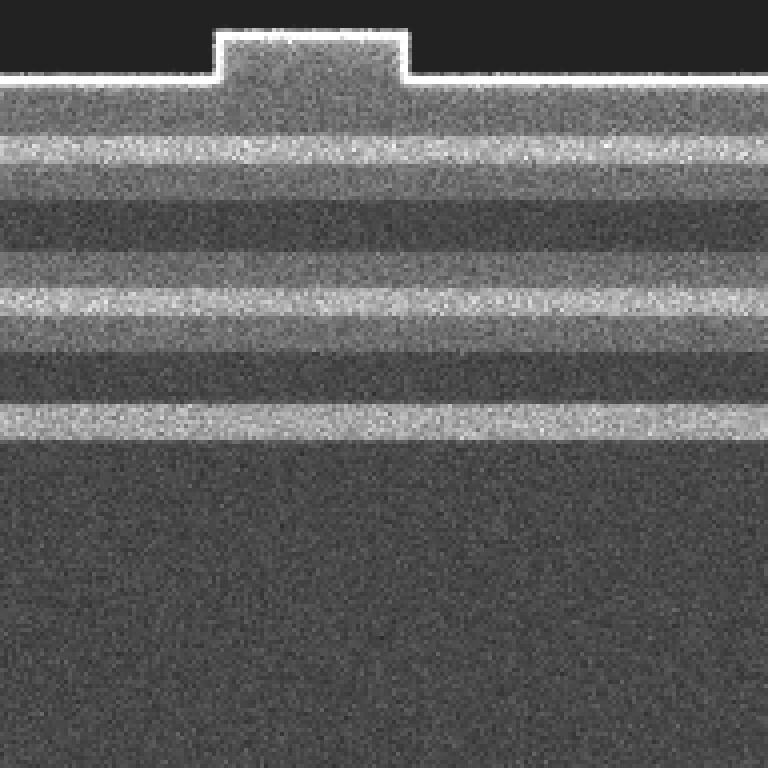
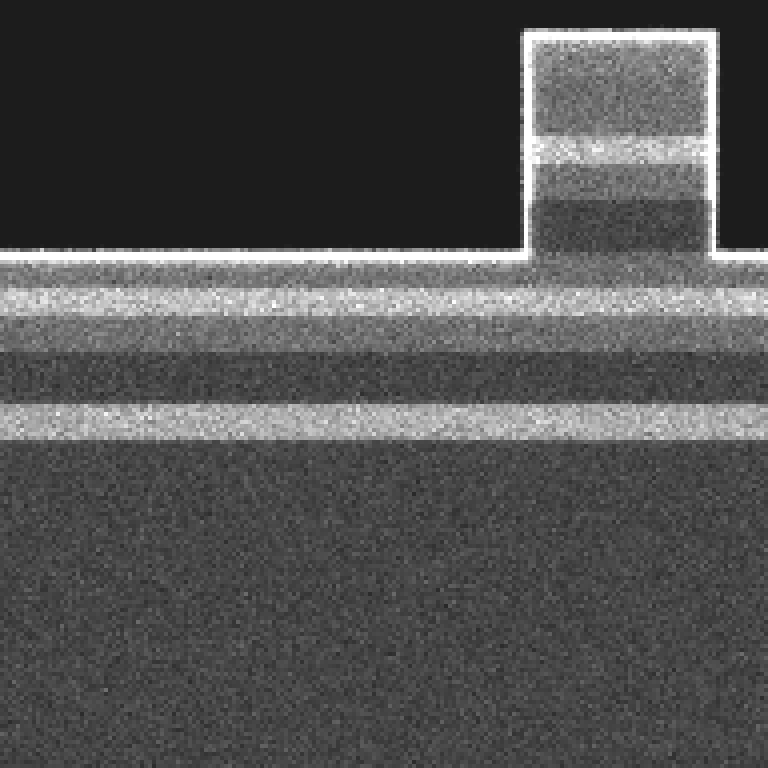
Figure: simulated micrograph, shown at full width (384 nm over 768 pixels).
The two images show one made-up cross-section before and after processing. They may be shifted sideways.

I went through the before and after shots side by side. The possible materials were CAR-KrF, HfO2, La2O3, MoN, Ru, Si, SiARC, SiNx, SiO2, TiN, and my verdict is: removed, Ru and Si and SiNx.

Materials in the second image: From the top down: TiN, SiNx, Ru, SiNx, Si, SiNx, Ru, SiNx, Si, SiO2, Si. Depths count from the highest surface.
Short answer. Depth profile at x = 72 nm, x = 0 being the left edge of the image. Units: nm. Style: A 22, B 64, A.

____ empty 110, SiNx 18, Ru 14, SiNx 18, Si 26, SiO2 18, Si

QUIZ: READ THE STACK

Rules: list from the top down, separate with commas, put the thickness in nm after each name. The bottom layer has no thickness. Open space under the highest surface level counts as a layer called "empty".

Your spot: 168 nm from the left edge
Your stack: empty 110, SiNx 18, Ru 14, SiNx 18, Si 26, SiO2 18, Si